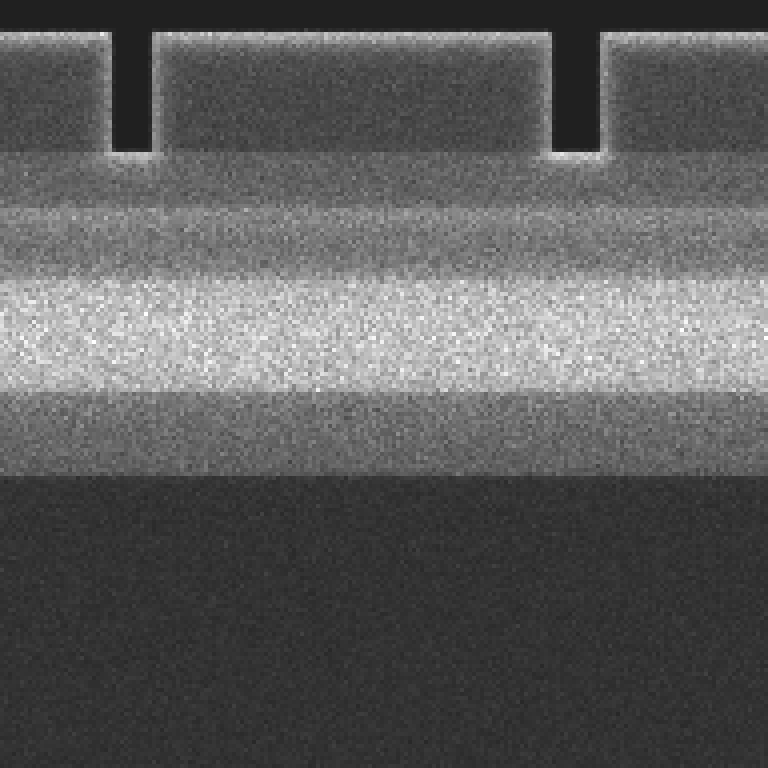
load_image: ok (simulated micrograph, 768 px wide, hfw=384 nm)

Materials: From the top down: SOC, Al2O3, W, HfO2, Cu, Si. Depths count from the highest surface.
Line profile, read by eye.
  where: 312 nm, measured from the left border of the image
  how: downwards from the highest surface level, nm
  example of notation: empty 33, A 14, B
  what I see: SOC 60, Al2O3 28, W 36, HfO2 56, Cu 42, Si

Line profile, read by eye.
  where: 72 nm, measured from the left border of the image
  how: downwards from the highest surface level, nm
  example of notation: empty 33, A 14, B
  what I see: empty 60, Al2O3 28, W 36, HfO2 56, Cu 42, Si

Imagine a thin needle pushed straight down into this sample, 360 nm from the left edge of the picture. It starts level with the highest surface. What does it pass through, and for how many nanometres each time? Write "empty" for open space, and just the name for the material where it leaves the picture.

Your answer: SOC 60, Al2O3 28, W 36, HfO2 56, Cu 42, Si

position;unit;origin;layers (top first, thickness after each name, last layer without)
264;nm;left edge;SOC 60, Al2O3 28, W 36, HfO2 56, Cu 42, Si